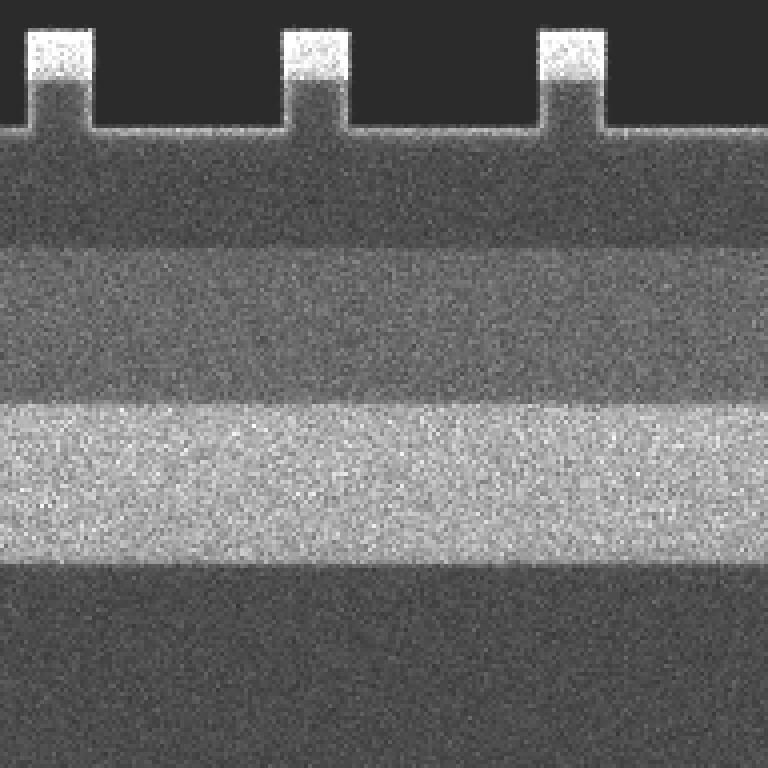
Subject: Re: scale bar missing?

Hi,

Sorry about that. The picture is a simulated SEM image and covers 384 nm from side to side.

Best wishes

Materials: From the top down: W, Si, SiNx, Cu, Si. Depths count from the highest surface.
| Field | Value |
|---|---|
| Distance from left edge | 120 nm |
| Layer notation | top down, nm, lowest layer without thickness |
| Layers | empty 48, Si 60, SiNx 78, Cu 80, Si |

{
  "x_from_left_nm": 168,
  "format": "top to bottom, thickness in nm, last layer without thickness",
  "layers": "W 24, Si 84, SiNx 78, Cu 80, Si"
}